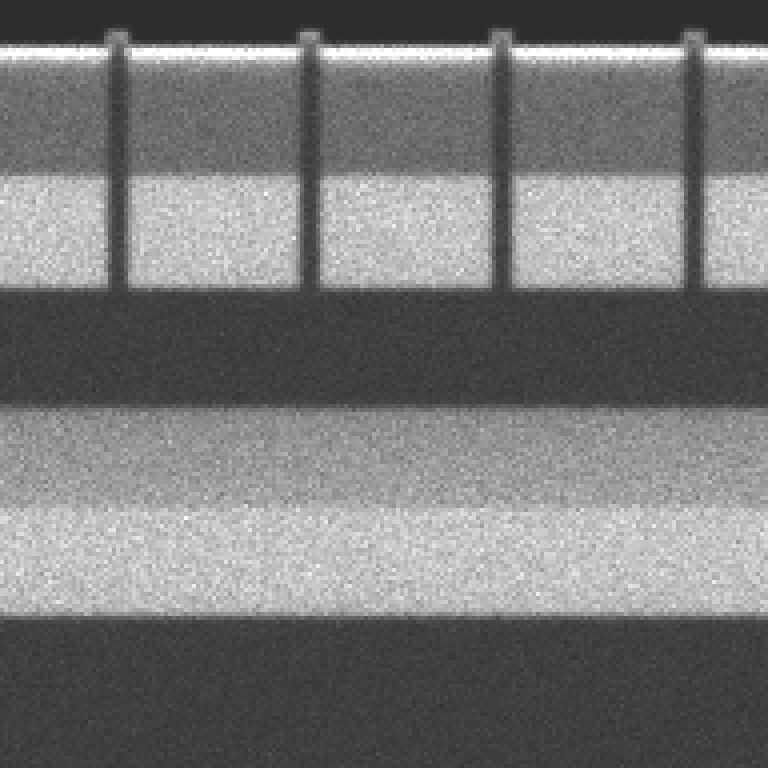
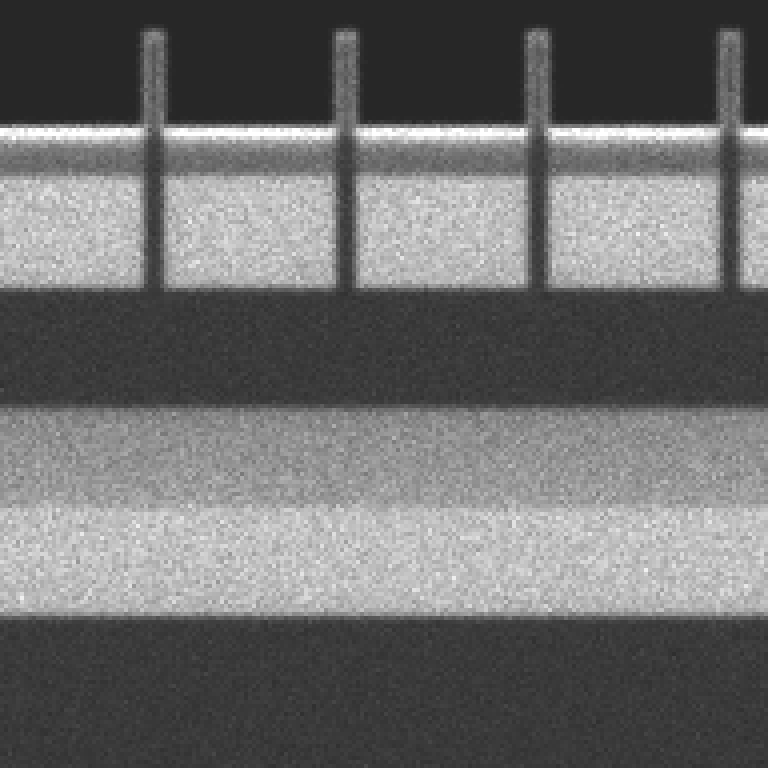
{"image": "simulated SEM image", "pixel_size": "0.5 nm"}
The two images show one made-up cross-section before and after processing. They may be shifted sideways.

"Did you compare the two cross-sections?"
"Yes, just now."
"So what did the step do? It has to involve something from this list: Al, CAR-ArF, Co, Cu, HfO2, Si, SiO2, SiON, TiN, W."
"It removed SiO2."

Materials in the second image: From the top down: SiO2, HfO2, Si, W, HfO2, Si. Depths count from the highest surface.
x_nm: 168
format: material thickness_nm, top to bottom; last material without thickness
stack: Si 188, W 50, HfO2 54, Si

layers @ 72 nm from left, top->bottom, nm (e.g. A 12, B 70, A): Si 188, W 50, HfO2 54, Si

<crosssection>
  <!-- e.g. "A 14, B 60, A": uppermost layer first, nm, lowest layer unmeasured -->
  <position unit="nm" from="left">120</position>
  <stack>empty 48, SiO2 24, HfO2 56, Si 60, W 50, HfO2 54, Si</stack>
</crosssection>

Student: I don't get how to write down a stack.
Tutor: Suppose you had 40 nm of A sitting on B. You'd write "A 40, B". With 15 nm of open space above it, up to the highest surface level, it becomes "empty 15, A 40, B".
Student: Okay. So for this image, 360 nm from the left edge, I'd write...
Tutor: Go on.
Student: Si 188, W 50, HfO2 54, Si